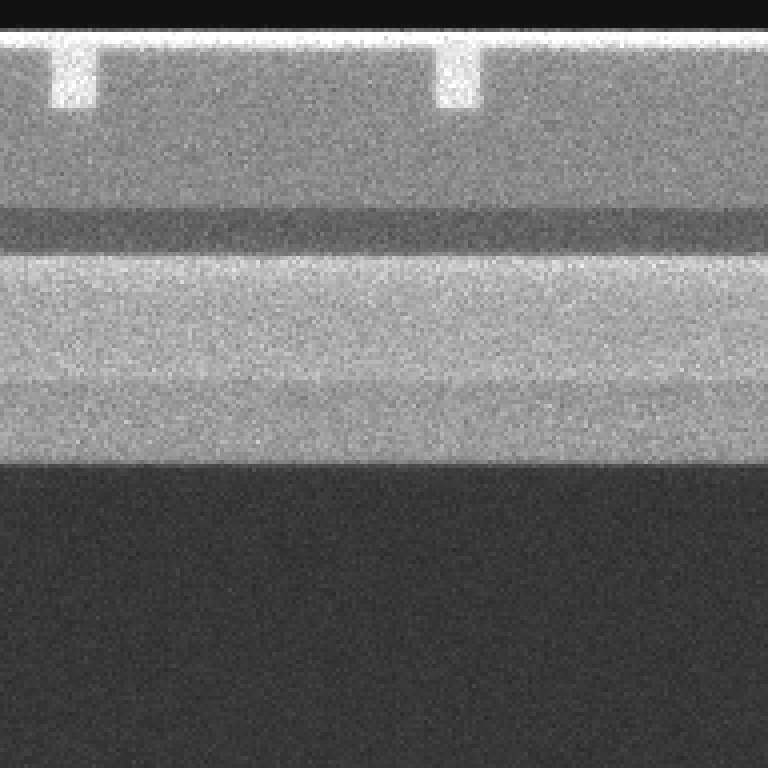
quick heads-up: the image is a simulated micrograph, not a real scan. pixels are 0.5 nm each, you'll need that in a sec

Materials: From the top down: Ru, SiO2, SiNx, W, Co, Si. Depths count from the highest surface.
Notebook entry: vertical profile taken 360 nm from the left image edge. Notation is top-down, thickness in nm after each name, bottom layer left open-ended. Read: Ru 8, SiO2 80, SiNx 24, W 62, Co 42, Si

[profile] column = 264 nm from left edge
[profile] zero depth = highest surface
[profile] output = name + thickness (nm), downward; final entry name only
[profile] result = Ru 8, SiO2 80, SiNx 24, W 62, Co 42, Si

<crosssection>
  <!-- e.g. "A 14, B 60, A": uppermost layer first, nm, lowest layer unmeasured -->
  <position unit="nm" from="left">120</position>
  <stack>Ru 8, SiO2 80, SiNx 24, W 62, Co 42, Si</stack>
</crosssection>